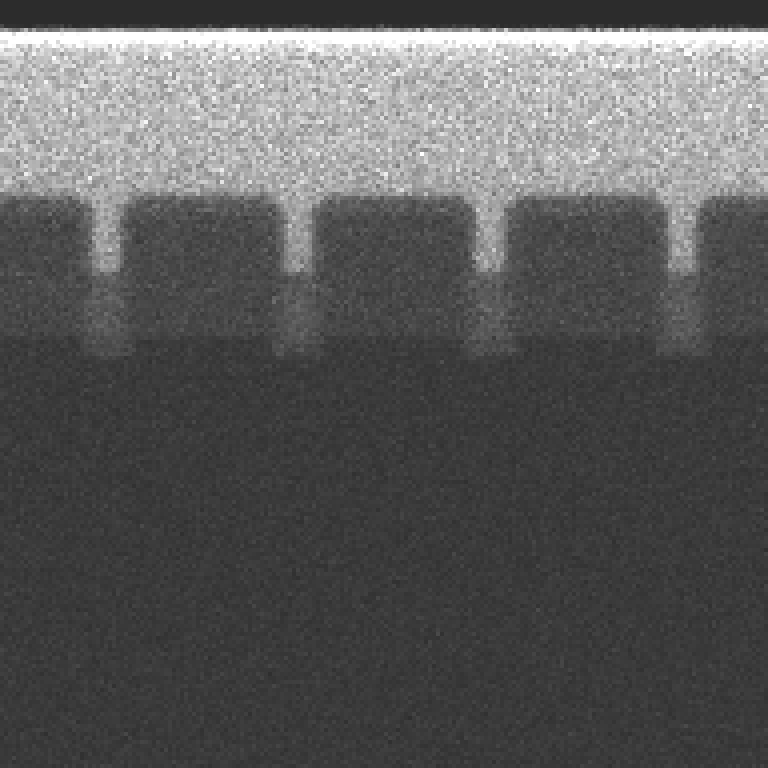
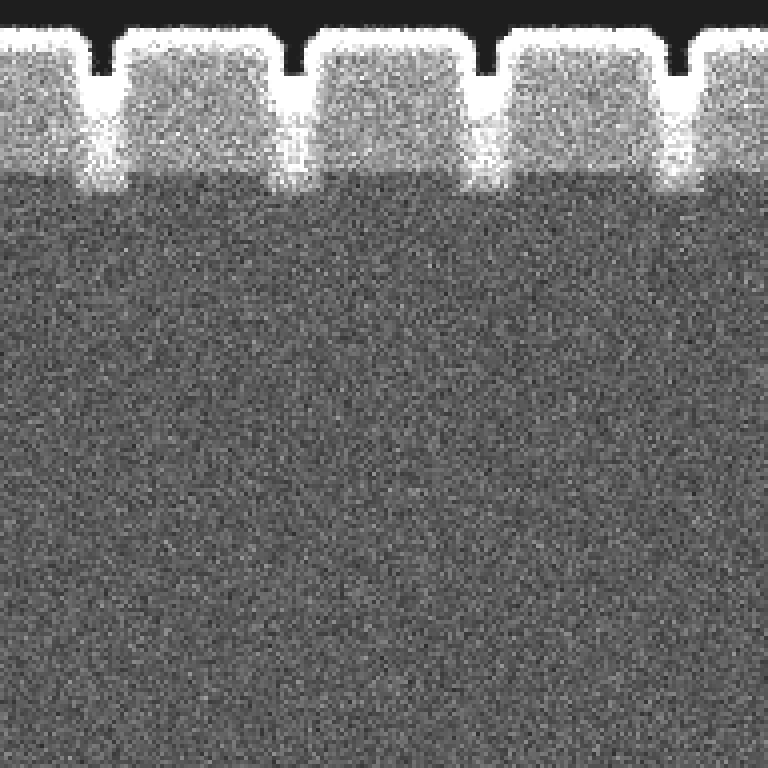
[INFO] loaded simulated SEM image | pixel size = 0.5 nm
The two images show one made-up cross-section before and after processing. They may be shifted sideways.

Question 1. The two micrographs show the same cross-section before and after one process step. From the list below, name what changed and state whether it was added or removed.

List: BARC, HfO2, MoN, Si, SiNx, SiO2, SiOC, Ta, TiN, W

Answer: HfO2, removed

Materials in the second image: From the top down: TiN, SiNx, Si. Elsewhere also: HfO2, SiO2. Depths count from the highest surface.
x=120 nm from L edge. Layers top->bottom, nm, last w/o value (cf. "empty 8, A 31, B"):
TiN 10, SiNx 60, Si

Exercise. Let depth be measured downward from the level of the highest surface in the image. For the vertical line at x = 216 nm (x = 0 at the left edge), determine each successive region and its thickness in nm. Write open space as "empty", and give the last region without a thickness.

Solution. TiN 10, SiNx 60, Si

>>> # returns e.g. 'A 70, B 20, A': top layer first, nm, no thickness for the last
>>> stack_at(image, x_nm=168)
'TiN 10, SiNx 60, Si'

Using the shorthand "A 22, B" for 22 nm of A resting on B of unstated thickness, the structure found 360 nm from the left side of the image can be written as TiN 10, SiNx 60, Si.